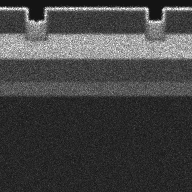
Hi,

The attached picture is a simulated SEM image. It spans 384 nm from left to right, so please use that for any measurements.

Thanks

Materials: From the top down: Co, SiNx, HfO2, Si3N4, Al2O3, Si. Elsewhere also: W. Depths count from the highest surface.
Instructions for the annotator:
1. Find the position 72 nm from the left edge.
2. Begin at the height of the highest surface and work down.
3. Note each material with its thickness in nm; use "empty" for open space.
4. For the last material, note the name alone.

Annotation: empty 30, W 30, Co 6, HfO2 36, Si3N4 46, Al2O3 28, Si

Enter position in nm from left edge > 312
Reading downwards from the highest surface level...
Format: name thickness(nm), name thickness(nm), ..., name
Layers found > empty 28, W 32, Co 6, HfO2 36, Si3N4 46, Al2O3 28, Si